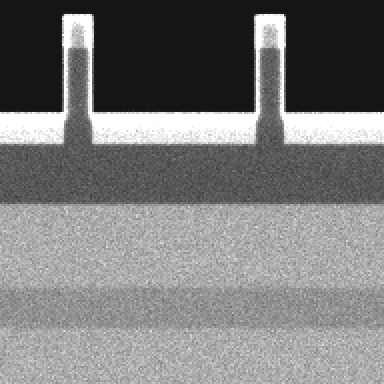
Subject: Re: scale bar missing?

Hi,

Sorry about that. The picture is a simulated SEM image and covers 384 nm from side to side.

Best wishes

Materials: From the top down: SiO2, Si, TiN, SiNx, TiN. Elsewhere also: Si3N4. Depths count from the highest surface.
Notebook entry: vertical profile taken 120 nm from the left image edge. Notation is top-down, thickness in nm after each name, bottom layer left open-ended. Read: empty 98, SiO2 30, Si 60, TiN 84, SiNx 40, TiN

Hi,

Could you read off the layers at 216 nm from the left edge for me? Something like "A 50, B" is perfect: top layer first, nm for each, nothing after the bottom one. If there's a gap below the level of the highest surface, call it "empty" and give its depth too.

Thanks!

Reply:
empty 98, SiO2 30, Si 60, TiN 84, SiNx 40, TiN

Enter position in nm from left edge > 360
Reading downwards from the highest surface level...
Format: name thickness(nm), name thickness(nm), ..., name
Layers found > empty 98, SiO2 30, Si 60, TiN 84, SiNx 40, TiN